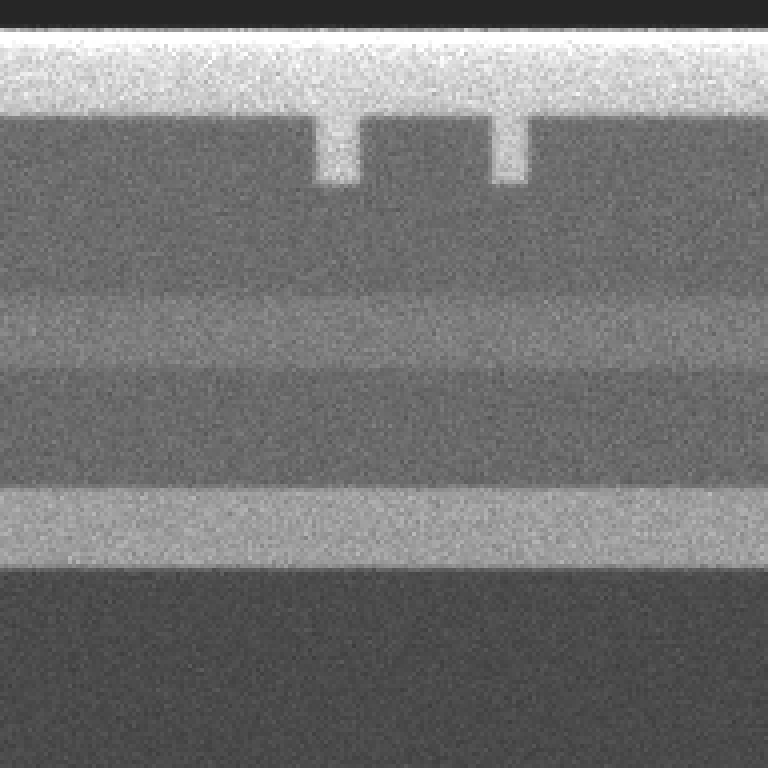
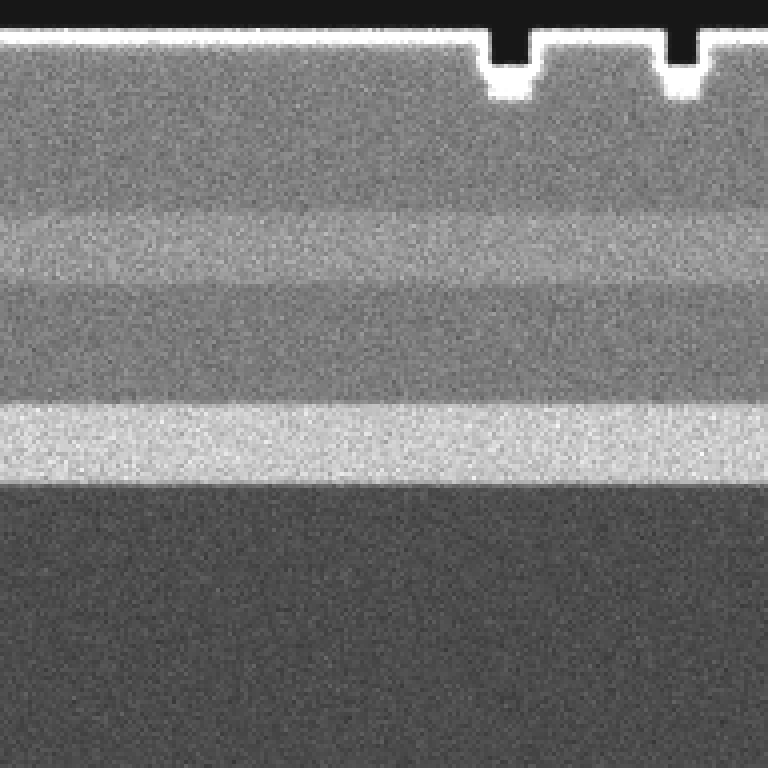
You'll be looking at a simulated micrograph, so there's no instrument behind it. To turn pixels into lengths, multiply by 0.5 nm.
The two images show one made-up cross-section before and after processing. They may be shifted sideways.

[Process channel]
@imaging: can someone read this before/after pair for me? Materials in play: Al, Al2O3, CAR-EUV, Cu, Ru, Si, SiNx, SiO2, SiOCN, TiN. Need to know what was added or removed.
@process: Ru removed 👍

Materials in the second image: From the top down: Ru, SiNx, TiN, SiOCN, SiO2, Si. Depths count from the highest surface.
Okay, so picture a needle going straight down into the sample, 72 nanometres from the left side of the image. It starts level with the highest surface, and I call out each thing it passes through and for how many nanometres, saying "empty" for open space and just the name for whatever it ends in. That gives SiNx 90, TiN 36, SiOCN 60, SiO2 40, Si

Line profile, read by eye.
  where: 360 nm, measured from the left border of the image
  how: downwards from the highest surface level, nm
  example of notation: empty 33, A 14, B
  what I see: SiNx 90, TiN 36, SiOCN 60, SiO2 40, Si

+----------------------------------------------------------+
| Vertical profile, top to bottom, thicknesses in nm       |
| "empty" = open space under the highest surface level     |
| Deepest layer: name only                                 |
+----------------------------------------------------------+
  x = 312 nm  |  SiNx 90, TiN 36, SiOCN 60, SiO2 40, Si